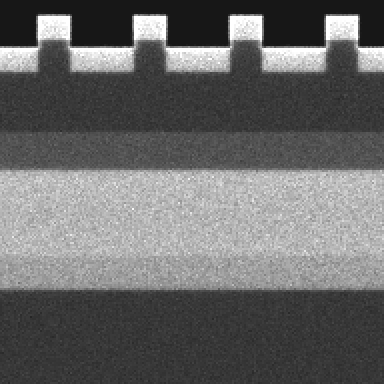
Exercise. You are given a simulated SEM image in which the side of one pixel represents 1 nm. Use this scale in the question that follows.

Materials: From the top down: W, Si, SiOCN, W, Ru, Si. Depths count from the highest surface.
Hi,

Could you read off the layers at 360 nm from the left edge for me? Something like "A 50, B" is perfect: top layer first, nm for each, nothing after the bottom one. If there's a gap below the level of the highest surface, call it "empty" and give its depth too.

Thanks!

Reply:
empty 32, W 24, Si 60, SiOCN 38, W 86, Ru 34, Si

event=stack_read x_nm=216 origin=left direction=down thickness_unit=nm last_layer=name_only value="empty 32, W 24, Si 60, SiOCN 38, W 86, Ru 34, Si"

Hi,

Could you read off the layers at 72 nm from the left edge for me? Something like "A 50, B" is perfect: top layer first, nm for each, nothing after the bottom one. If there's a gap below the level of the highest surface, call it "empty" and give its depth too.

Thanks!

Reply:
empty 32, W 24, Si 60, SiOCN 38, W 86, Ru 34, Si